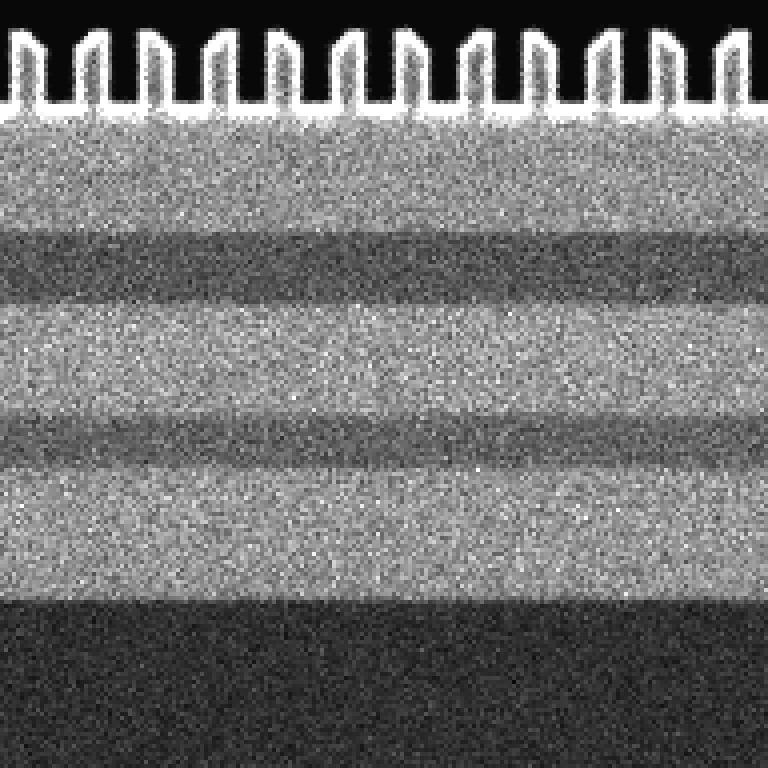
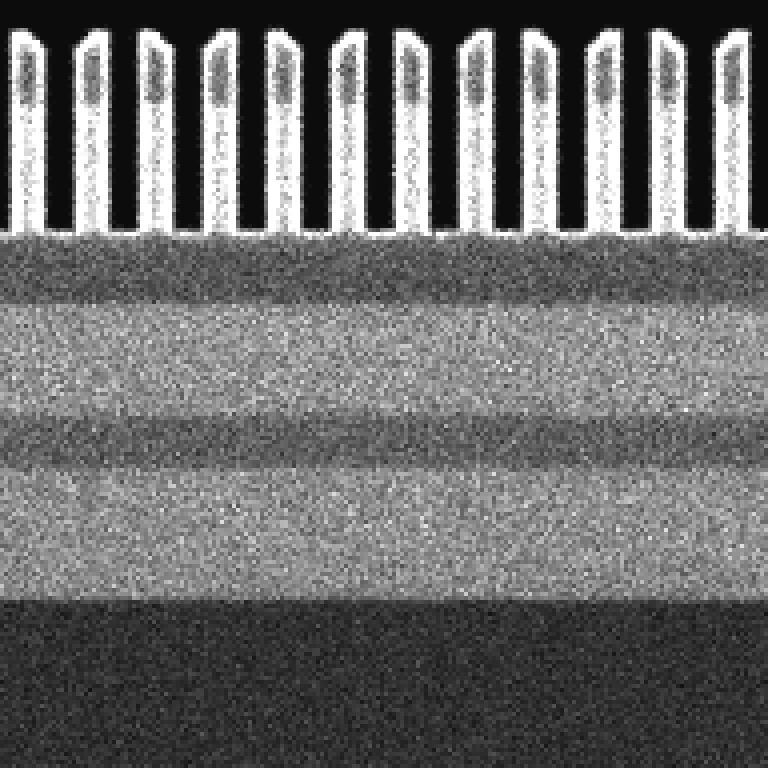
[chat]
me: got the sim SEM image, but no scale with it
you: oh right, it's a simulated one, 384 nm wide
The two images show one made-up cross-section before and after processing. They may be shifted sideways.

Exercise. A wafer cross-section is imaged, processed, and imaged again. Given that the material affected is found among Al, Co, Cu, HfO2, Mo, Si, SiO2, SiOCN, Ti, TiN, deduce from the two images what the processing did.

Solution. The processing removed SiO2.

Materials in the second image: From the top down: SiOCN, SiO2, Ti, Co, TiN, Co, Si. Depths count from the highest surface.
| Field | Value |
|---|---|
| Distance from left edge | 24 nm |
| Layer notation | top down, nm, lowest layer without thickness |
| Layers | empty 100, Ti 36, Co 56, TiN 26, Co 66, Si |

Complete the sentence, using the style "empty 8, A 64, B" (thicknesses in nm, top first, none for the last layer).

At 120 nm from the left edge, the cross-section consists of empty 100, Ti 36, Co 56, TiN 26, Co 66, Si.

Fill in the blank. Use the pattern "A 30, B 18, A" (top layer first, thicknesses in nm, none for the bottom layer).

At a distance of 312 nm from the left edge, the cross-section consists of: empty 100, Ti 36, Co 56, TiN 26, Co 66, Si